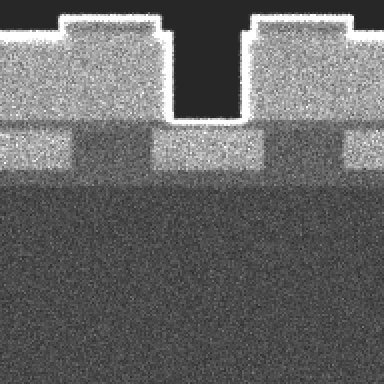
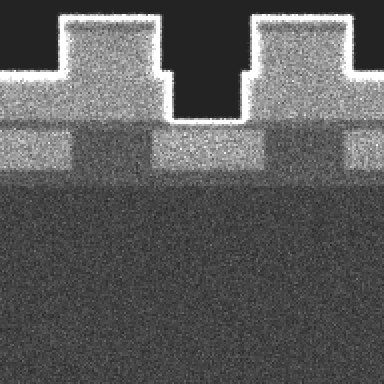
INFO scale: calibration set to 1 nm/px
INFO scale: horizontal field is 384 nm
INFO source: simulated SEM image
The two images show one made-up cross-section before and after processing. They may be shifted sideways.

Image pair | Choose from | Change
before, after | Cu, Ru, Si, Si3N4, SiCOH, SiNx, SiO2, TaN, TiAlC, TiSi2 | SiO2 (removed)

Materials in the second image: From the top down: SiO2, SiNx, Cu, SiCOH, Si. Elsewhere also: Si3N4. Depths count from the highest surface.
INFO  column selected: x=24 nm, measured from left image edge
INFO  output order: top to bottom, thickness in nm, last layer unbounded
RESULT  empty 56, SiO2 48, SiNx 10, Cu 40, SiCOH 16, Si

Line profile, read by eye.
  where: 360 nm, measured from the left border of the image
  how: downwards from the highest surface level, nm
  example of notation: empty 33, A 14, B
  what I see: empty 56, SiO2 48, SiNx 10, Cu 40, SiCOH 16, Si